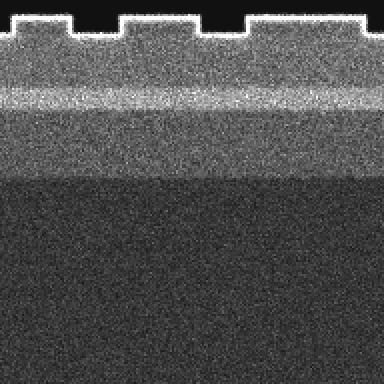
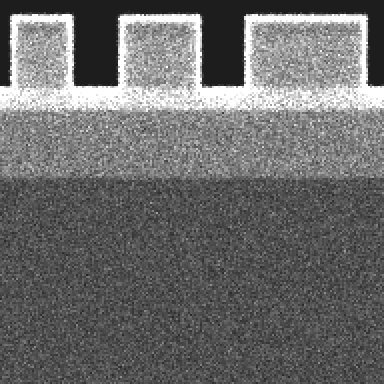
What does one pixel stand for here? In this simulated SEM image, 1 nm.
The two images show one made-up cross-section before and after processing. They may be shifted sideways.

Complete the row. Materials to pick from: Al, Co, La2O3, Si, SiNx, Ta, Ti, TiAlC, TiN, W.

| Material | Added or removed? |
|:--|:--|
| TiN | removed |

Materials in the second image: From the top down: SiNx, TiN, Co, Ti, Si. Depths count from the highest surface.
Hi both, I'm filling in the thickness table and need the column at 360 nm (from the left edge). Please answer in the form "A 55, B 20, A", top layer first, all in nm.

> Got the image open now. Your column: SiNx 18, TiN 54, Co 22, Ti 68, Si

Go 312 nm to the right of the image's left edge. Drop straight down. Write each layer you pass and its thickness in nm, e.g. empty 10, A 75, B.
SiNx 18, TiN 54, Co 22, Ti 68, Si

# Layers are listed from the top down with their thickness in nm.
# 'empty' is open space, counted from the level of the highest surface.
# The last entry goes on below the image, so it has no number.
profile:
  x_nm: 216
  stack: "empty 72, Co 22, Ti 68, Si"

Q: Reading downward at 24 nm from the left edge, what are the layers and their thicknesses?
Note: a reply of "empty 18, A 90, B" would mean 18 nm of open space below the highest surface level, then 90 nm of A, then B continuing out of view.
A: SiNx 18, TiN 54, Co 22, Ti 68, Si